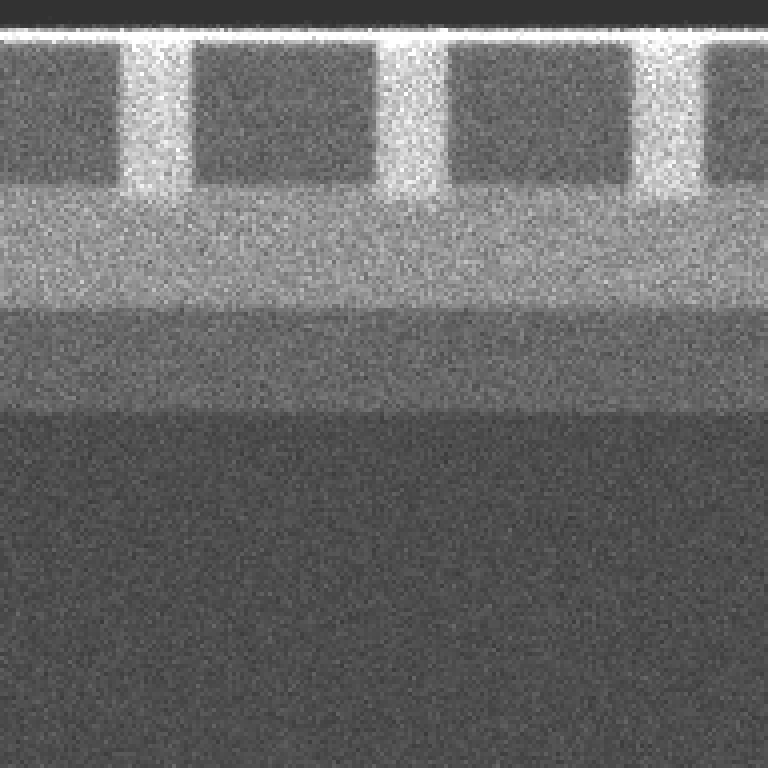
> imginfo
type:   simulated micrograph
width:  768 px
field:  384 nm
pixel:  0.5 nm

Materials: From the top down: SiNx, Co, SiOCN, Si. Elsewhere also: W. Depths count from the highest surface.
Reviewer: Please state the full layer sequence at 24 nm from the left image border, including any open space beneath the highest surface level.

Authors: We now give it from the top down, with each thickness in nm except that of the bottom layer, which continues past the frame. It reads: SiNx 76, Co 62, SiOCN 52, Si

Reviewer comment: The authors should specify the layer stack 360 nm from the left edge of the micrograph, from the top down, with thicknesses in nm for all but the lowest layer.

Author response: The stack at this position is SiNx 76, Co 62, SiOCN 52, Si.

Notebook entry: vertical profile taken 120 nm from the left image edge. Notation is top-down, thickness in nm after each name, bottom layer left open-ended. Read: SiNx 76, Co 62, SiOCN 52, Si